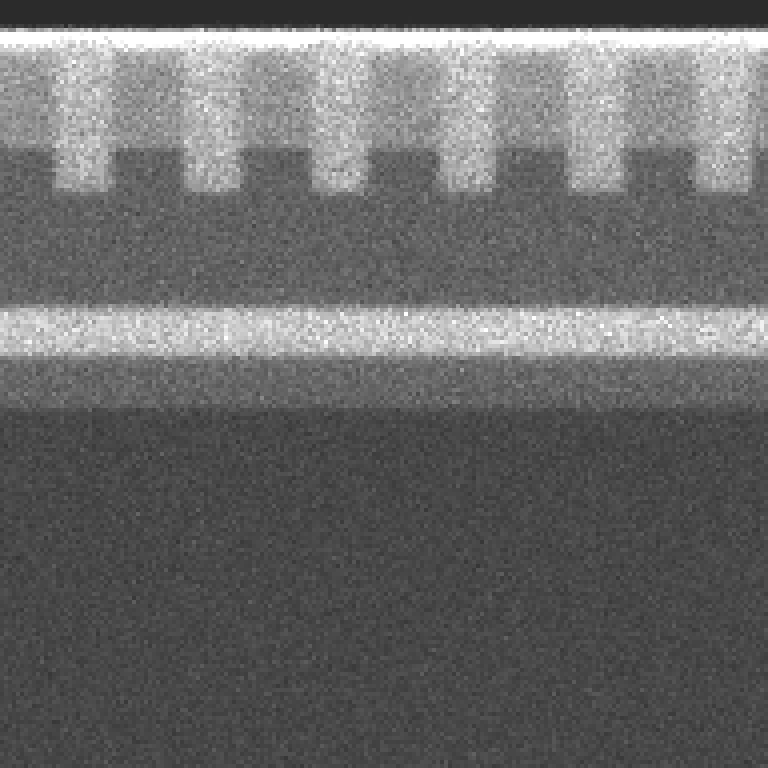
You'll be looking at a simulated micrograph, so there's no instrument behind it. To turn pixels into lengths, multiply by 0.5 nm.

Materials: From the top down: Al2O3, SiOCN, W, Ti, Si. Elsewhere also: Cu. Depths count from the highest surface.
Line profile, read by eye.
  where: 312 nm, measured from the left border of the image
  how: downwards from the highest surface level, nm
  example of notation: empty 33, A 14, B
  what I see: Al2O3 58, SiOCN 80, W 24, Ti 26, Si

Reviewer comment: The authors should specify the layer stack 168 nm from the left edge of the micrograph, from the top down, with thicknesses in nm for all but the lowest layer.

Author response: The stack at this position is Cu 80, SiOCN 58, W 24, Ti 26, Si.